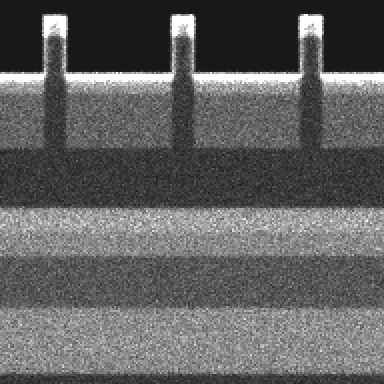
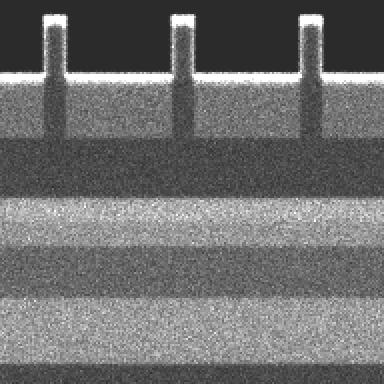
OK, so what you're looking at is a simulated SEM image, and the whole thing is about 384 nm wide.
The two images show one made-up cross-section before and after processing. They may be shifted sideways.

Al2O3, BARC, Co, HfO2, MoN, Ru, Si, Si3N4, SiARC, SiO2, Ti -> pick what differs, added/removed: Al2O3 removed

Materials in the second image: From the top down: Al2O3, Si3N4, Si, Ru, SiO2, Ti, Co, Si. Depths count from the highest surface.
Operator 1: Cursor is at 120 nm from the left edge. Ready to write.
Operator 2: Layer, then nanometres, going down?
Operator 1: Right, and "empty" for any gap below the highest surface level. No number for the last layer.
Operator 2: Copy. empty 58, Al2O3 10, Si3N4 54, Si 60, Ru 24, SiO2 24, Ti 52, Co 66, Si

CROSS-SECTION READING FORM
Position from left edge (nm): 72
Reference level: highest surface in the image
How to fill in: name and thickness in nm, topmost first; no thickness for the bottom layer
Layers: empty 58, Al2O3 10, Si3N4 54, Si 60, Ru 24, SiO2 24, Ti 52, Co 66, Si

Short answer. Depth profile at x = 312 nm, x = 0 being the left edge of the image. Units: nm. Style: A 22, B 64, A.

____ Al2O3 10, Si 172, Ru 24, SiO2 24, Ti 52, Co 66, Si